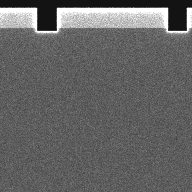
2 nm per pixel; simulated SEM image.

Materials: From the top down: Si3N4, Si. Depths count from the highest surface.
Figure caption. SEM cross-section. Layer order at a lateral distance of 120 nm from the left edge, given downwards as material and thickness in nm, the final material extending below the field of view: Si3N4 40, Si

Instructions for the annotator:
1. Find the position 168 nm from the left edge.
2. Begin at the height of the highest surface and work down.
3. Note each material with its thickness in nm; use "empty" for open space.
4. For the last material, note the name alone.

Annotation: Si3N4 40, Si